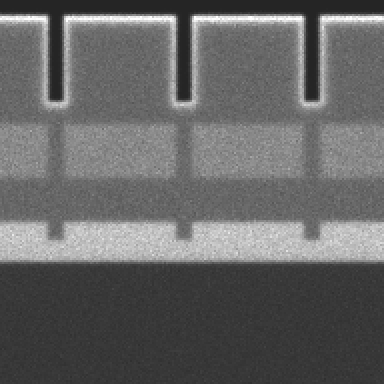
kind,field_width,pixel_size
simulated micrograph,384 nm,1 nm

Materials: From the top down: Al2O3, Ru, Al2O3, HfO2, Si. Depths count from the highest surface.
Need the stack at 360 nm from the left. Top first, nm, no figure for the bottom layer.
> Al2O3 108, Ru 54, Al2O3 44, HfO2 40, Si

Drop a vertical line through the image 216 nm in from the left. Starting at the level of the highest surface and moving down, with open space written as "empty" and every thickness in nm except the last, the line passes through Al2O3 108, Ru 54, Al2O3 44, HfO2 40, Si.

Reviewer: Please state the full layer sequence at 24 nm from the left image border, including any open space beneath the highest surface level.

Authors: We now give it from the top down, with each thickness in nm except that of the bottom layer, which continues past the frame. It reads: Al2O3 108, Ru 54, Al2O3 44, HfO2 40, Si